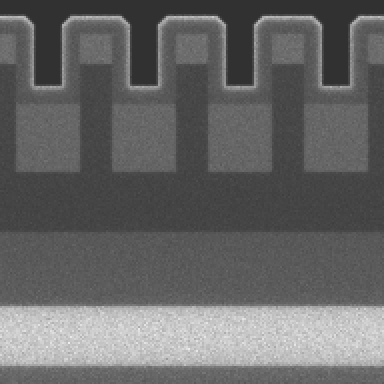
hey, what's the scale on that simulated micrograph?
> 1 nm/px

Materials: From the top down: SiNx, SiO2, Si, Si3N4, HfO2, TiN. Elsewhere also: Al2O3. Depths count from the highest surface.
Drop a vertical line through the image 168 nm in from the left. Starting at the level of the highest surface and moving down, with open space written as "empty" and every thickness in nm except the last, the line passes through SiNx 88, SiO2 68, Si 60, Si3N4 74, HfO2 60, TiN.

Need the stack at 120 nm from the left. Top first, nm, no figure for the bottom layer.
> SiNx 88, SiO2 68, Si 60, Si3N4 74, HfO2 60, TiN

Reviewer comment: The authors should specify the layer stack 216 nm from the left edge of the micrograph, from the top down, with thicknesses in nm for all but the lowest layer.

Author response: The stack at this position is SiNx 88, SiO2 68, Si 60, Si3N4 74, HfO2 60, TiN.